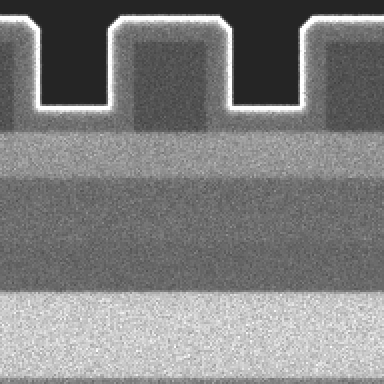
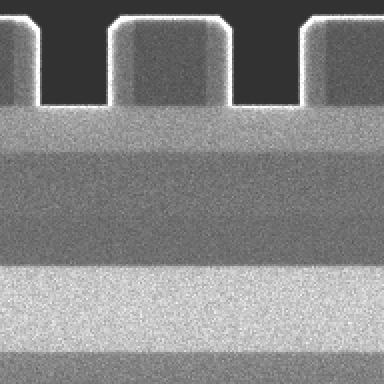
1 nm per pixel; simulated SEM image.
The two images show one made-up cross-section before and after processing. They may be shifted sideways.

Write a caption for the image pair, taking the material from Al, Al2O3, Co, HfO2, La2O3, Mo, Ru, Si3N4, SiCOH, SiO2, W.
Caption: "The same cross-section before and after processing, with Al2O3 removed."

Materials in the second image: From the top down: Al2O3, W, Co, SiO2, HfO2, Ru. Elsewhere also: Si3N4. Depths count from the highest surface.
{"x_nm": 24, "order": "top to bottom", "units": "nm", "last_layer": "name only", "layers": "Al2O3 90, W 46, Co 64, SiO2 50, HfO2 86, Ru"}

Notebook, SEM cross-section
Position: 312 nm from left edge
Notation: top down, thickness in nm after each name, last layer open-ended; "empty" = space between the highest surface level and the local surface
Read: Al2O3 90, W 46, Co 64, SiO2 50, HfO2 86, Ru